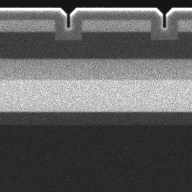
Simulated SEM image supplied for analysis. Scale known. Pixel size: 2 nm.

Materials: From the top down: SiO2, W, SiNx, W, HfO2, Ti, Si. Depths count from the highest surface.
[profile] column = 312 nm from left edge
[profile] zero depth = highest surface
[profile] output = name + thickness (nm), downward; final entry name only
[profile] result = SiO2 64, SiNx 38, W 42, HfO2 64, Ti 26, Si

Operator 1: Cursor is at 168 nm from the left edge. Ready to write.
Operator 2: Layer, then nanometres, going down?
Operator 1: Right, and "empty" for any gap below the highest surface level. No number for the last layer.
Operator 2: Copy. SiO2 24, W 24, SiNx 54, W 42, HfO2 64, Ti 26, Si